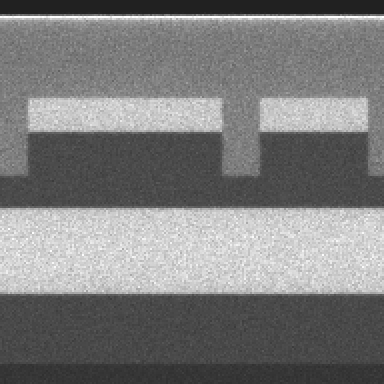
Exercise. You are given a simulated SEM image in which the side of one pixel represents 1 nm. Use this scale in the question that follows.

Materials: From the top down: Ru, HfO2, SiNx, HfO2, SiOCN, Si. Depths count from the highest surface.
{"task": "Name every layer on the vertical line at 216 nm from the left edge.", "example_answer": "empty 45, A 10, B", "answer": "Ru 82, HfO2 34, SiNx 76, HfO2 86, SiOCN 70, Si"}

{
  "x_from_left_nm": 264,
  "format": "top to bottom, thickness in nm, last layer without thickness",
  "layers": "Ru 82, HfO2 34, SiNx 76, HfO2 86, SiOCN 70, Si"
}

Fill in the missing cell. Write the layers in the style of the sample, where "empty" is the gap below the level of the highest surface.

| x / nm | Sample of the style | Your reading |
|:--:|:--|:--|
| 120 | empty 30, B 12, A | Ru 82, HfO2 34, SiNx 76, HfO2 86, SiOCN 70, Si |